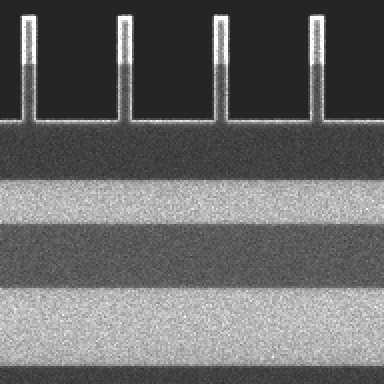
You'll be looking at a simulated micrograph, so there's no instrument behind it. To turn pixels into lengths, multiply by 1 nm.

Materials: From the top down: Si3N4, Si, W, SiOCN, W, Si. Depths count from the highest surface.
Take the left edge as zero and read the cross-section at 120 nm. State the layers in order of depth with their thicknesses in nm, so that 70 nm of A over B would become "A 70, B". Si3N4 48, Si 116, W 44, SiOCN 64, W 78, Si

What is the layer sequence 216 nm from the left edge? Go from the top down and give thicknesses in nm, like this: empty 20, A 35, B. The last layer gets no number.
Si3N4 48, Si 116, W 44, SiOCN 64, W 78, Si